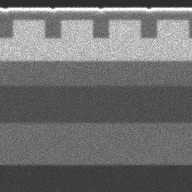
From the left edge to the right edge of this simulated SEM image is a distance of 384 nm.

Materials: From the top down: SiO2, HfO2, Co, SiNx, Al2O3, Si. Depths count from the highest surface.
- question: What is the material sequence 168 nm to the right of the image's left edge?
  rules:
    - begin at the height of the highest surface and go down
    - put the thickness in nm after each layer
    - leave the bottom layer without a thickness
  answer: SiO2 24, HfO2 82, Co 50, SiNx 74, Al2O3 84, Si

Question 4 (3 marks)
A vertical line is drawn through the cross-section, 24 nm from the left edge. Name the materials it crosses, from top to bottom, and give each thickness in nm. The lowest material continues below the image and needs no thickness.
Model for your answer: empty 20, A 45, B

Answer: SiO2 60, HfO2 46, Co 50, SiNx 74, Al2O3 84, Si